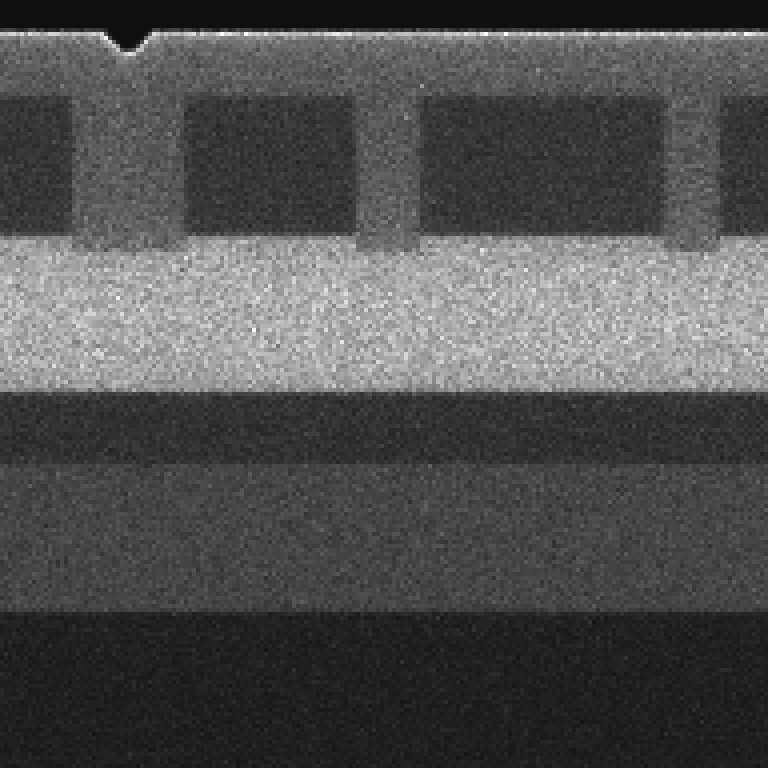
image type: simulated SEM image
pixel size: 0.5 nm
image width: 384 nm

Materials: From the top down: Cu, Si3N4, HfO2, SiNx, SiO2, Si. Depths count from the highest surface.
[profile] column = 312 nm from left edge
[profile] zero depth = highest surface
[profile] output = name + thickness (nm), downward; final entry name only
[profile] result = Cu 32, Si3N4 70, HfO2 78, SiNx 36, SiO2 74, Si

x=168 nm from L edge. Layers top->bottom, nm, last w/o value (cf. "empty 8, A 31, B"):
Cu 32, Si3N4 70, HfO2 78, SiNx 36, SiO2 74, Si